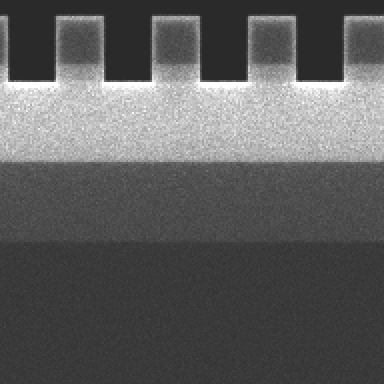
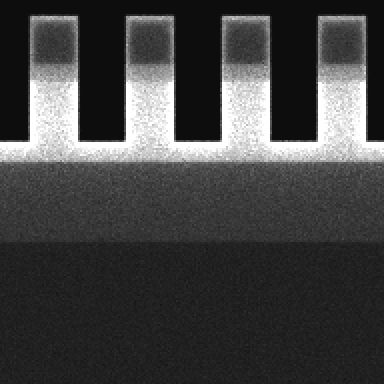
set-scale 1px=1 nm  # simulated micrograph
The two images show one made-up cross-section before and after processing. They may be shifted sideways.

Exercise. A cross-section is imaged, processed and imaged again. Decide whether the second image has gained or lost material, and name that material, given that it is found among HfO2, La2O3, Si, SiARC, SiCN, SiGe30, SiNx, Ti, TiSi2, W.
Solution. removed: HfO2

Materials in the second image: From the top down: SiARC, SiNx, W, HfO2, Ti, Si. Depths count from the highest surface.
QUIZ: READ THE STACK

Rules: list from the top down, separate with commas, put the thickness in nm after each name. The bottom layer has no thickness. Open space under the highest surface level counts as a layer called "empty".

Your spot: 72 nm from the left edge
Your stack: SiARC 16, SiNx 32, W 18, HfO2 80, Ti 80, Si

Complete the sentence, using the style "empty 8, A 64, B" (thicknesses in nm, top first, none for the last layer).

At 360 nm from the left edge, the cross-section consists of SiARC 16, SiNx 32, W 18, HfO2 80, Ti 80, Si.